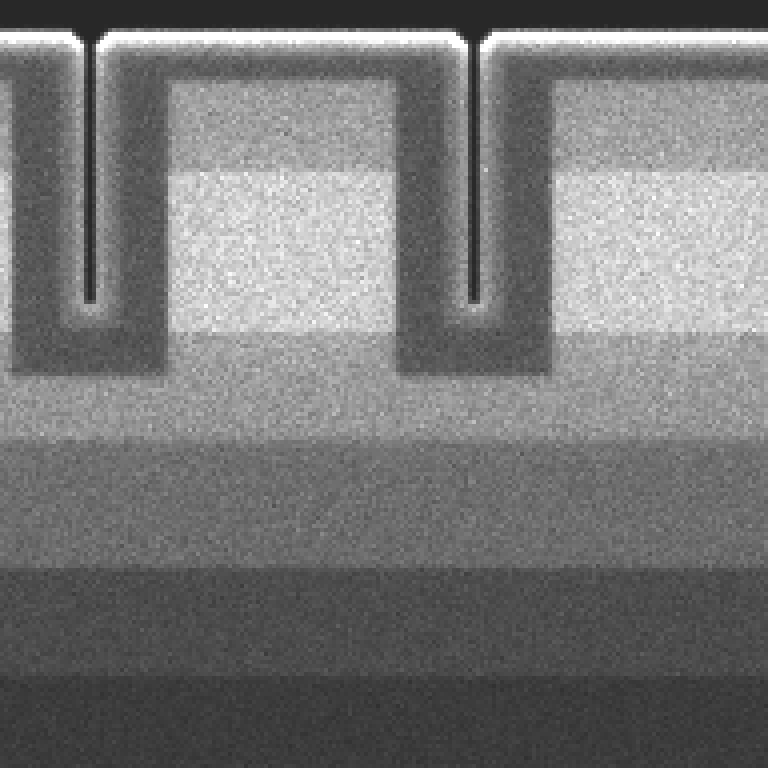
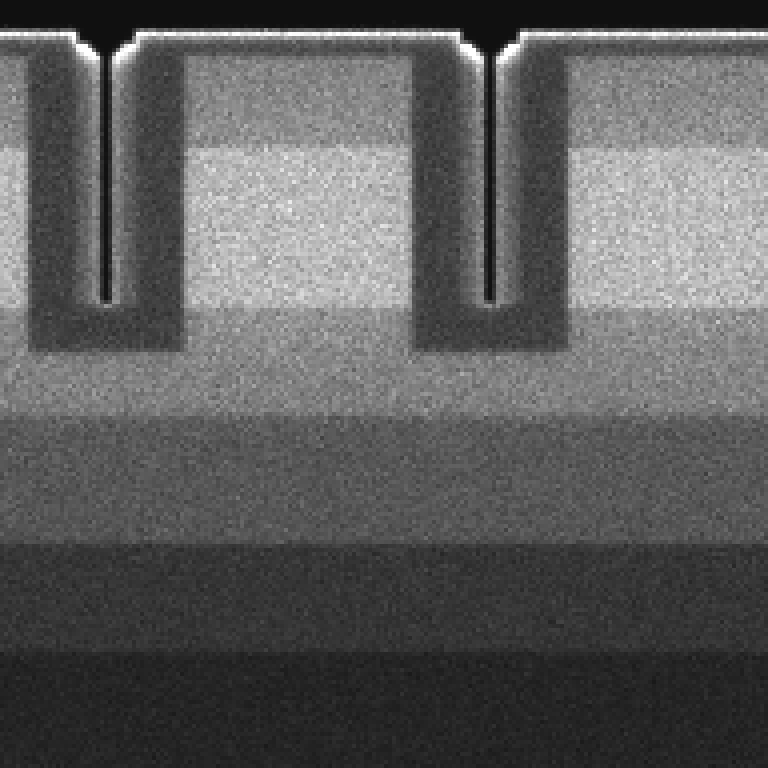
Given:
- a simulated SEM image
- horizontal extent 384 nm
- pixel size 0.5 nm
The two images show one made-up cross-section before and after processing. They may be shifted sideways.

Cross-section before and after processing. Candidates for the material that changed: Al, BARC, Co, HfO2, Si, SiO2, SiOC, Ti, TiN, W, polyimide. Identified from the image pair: SiO2 (removed).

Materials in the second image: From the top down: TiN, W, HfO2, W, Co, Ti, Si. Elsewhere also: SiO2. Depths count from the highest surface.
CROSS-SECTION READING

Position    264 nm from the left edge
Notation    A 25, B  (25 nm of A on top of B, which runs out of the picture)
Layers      TiN 160, W 32, Co 64, Ti 54, Si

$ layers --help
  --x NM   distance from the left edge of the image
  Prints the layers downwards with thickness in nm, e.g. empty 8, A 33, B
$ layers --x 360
TiN 12, W 46, HfO2 80, W 54, Co 64, Ti 54, Si